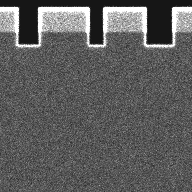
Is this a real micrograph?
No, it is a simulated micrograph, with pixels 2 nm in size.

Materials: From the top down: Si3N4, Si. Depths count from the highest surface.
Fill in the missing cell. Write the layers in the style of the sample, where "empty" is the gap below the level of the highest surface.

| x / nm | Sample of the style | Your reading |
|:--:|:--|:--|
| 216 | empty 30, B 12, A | Si3N4 48, Si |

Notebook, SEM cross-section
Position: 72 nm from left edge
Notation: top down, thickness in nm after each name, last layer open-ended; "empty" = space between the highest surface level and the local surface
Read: empty 74, Si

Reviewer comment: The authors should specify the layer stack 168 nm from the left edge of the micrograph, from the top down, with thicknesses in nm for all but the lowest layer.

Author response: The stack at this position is Si3N4 48, Si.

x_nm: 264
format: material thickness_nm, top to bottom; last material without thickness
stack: Si3N4 48, Si